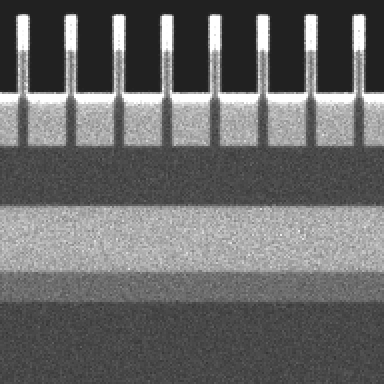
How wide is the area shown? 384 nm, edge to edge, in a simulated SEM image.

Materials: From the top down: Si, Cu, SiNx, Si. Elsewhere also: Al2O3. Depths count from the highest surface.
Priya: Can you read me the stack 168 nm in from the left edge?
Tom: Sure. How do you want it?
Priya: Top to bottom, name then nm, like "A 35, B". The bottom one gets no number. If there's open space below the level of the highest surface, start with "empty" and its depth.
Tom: Si 190, Cu 66, SiNx 30, Si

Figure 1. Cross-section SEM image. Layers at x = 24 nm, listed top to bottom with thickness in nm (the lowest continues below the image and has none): Si 190, Cu 66, SiNx 30, Si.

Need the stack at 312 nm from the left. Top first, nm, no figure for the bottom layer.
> Si 190, Cu 66, SiNx 30, Si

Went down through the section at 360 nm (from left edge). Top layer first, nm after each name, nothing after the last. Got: Si 190, Cu 66, SiNx 30, Si